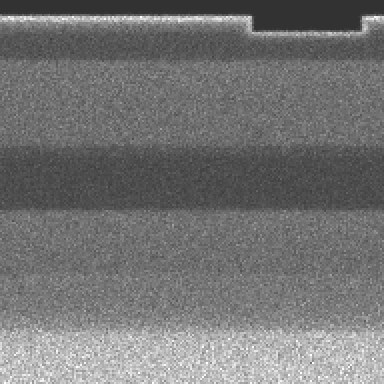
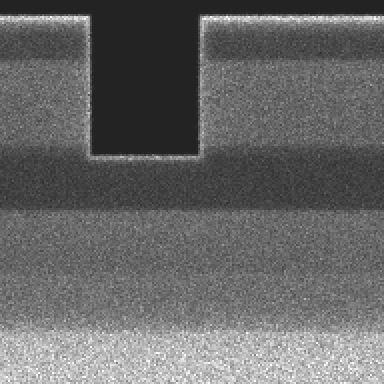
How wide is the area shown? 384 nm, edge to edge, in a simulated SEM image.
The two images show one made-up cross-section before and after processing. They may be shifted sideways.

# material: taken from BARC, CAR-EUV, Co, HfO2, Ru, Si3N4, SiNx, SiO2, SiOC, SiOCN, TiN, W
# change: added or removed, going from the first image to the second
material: Co and Si3N4 and TiN
change: removed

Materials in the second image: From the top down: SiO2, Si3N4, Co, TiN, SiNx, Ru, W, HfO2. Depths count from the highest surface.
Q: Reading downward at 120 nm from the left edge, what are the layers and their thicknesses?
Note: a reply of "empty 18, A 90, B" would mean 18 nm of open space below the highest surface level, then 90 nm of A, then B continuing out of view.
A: empty 140, SiNx 54, Ru 64, W 58, HfO2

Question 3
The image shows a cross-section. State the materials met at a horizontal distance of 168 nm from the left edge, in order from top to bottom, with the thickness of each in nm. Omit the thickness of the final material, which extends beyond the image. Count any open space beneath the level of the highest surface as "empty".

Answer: empty 140, SiNx 54, Ru 64, W 58, HfO2